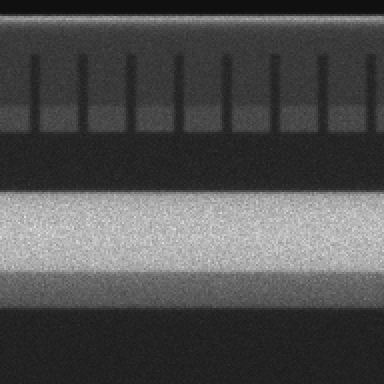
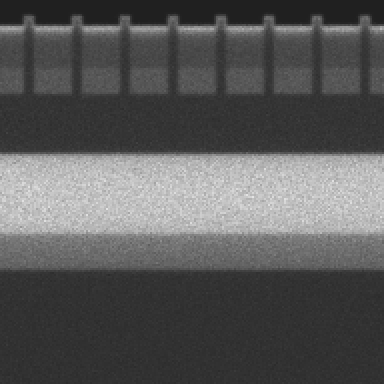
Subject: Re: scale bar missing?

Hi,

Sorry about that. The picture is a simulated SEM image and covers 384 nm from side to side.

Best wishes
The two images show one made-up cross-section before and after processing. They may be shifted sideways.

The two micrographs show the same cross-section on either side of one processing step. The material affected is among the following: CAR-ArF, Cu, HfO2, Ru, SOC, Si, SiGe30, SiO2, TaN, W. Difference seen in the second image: SOC removed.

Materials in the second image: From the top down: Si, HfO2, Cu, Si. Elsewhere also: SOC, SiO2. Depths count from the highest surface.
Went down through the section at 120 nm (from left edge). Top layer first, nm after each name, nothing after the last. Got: Si 138, HfO2 80, Cu 36, Si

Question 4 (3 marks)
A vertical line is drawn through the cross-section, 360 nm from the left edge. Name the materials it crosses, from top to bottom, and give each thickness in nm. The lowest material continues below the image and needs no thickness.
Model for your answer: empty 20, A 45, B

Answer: Si 138, HfO2 80, Cu 36, Si